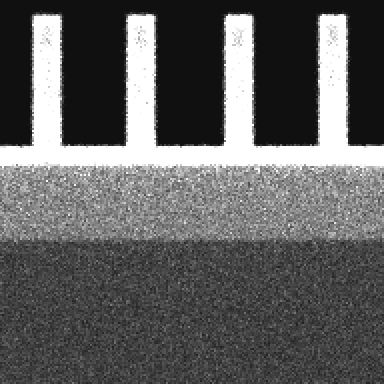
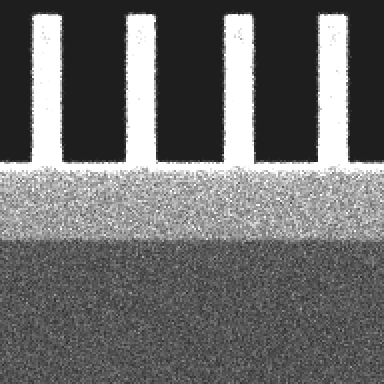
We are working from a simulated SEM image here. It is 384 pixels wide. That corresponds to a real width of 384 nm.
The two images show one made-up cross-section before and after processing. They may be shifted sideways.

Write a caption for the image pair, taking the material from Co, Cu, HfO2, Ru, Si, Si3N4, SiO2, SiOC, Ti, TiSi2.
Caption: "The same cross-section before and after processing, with HfO2 removed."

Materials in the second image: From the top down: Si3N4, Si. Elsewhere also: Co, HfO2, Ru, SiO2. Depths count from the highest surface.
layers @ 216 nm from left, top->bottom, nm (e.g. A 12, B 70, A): empty 148, Si3N4 76, Si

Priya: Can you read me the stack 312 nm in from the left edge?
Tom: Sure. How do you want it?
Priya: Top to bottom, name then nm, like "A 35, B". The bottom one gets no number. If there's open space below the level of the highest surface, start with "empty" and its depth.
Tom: empty 148, Si3N4 76, Si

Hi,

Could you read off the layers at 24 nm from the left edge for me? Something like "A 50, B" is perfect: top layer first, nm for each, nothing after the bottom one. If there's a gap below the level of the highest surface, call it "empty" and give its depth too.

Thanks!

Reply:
empty 148, Si3N4 76, Si